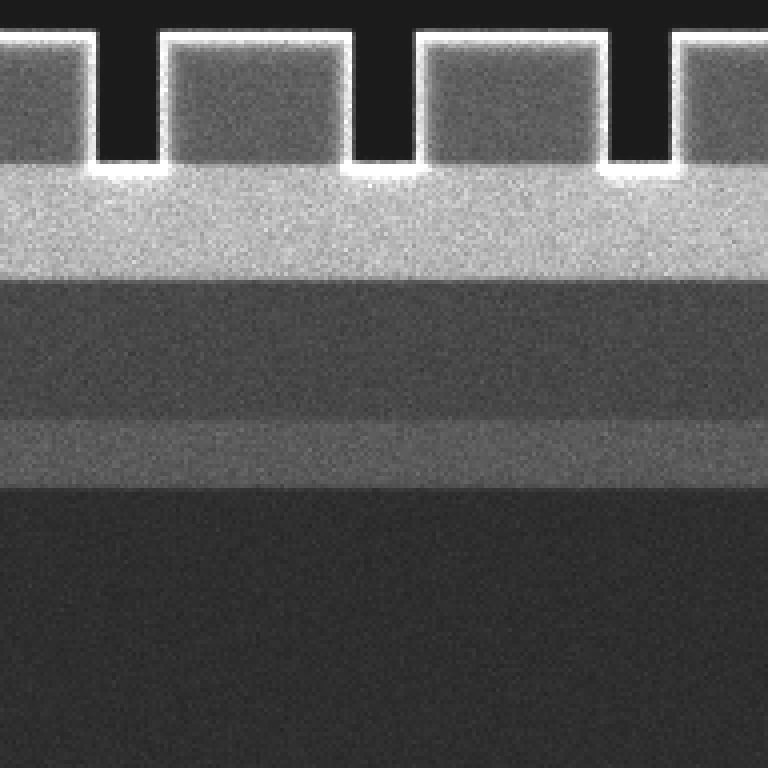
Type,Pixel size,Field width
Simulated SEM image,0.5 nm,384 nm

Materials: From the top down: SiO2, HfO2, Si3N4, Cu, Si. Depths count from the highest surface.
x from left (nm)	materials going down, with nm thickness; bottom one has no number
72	empty 66, HfO2 58, Si3N4 70, Cu 34, Si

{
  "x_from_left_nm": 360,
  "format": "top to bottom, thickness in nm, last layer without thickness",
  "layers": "SiO2 66, HfO2 58, Si3N4 70, Cu 34, Si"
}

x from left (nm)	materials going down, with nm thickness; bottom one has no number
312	empty 66, HfO2 58, Si3N4 70, Cu 34, Si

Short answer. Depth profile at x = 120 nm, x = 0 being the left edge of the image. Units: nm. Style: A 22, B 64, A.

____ SiO2 66, HfO2 58, Si3N4 70, Cu 34, Si